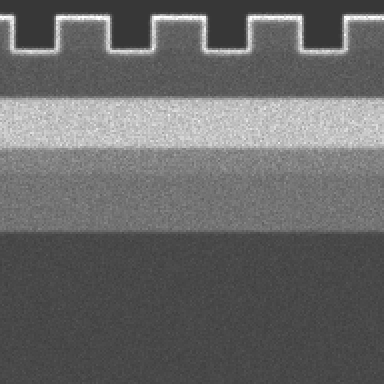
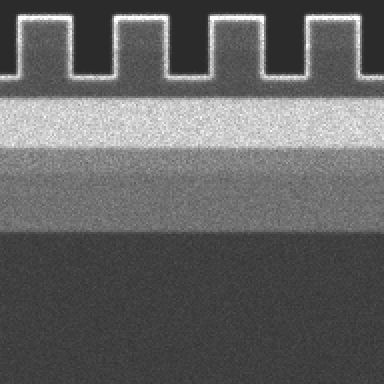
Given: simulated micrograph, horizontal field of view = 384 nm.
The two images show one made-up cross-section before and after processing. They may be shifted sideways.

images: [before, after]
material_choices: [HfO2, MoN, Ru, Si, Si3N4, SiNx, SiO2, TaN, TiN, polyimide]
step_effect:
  removed: SiNx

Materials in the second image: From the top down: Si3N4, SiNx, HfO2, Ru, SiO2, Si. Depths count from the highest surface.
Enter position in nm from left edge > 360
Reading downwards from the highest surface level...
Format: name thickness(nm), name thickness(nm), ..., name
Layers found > empty 60, SiNx 22, HfO2 50, Ru 26, SiO2 58, Si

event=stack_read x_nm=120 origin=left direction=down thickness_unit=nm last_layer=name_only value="Si3N4 34, SiNx 48, HfO2 50, Ru 26, SiO2 58, Si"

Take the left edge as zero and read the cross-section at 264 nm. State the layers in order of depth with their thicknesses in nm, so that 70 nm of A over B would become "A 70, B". empty 60, SiNx 22, HfO2 50, Ru 26, SiO2 58, Si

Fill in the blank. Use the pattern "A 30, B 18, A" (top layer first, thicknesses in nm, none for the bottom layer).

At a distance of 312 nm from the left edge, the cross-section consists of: Si3N4 34, SiNx 48, HfO2 50, Ru 26, SiO2 58, Si